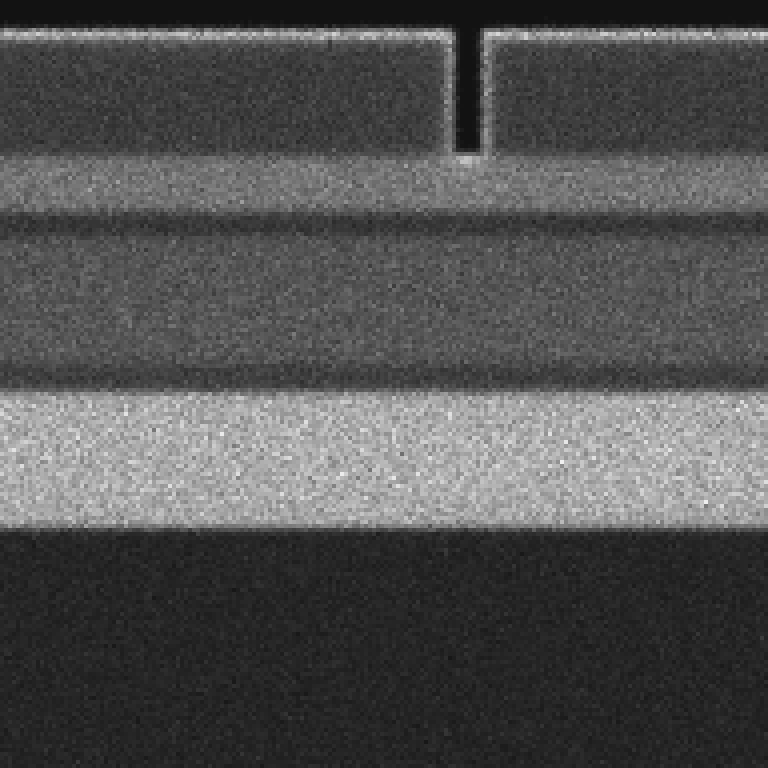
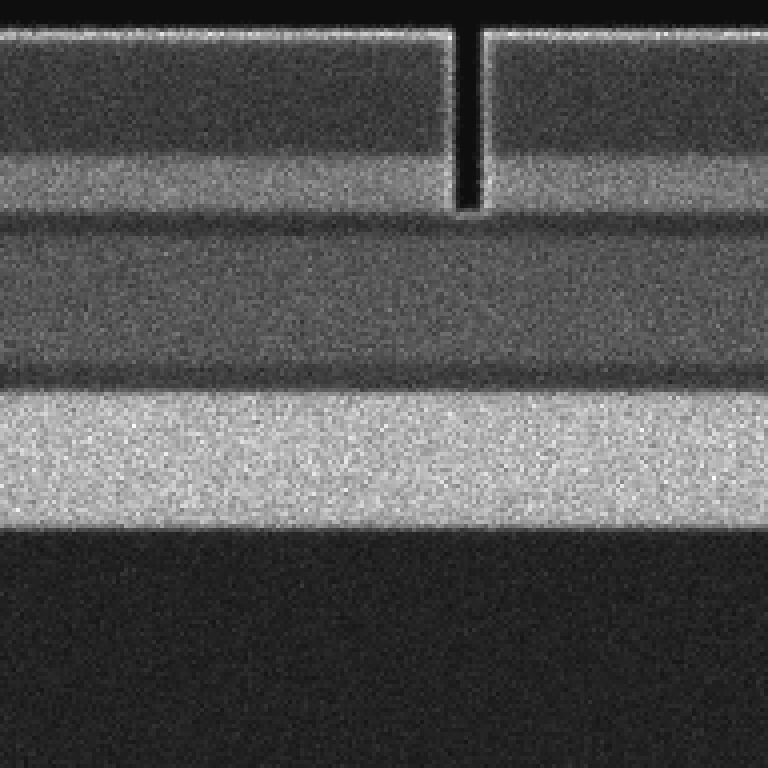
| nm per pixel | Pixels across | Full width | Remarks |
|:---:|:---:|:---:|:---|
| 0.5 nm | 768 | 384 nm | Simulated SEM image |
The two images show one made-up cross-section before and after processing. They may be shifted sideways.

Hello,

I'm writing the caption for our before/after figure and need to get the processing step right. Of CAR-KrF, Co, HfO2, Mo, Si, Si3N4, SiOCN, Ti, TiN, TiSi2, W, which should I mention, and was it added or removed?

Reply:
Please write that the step removed W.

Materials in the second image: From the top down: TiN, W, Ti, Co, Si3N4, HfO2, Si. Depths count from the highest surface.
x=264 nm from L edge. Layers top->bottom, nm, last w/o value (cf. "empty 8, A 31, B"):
TiN 62, W 28, Ti 12, Co 64, Si3N4 14, HfO2 68, Si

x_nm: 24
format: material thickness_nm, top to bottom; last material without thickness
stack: TiN 62, W 28, Ti 12, Co 64, Si3N4 14, HfO2 68, Si